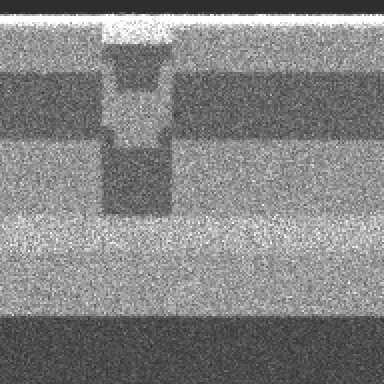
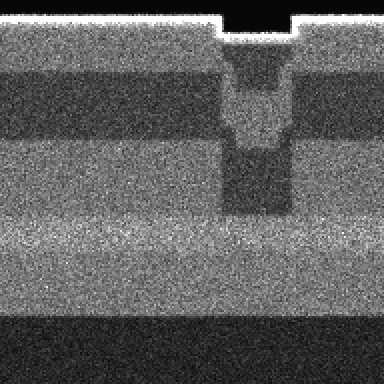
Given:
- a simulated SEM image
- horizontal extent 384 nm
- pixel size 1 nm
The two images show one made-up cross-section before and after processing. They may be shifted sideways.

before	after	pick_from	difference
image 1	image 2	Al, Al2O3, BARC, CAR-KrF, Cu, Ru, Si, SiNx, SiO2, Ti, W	W removed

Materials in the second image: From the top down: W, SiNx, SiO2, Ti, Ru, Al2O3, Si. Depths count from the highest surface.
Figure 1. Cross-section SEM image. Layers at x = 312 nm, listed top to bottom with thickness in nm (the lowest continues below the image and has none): SiO2 56, Ti 68, SiO2 76, Ru 36, Al2O3 64, Si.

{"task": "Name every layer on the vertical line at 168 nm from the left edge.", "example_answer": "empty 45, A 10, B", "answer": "SiO2 56, Ti 68, SiO2 76, Ru 36, Al2O3 64, Si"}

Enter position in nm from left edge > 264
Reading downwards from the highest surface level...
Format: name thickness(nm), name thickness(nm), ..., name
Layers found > empty 18, W 10, SiNx 48, SiO2 56, Ti 68, Ru 36, Al2O3 64, Si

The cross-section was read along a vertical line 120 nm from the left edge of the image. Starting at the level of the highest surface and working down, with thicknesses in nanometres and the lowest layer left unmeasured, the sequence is SiO2 56, Ti 68, SiO2 76, Ru 36, Al2O3 64, Si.